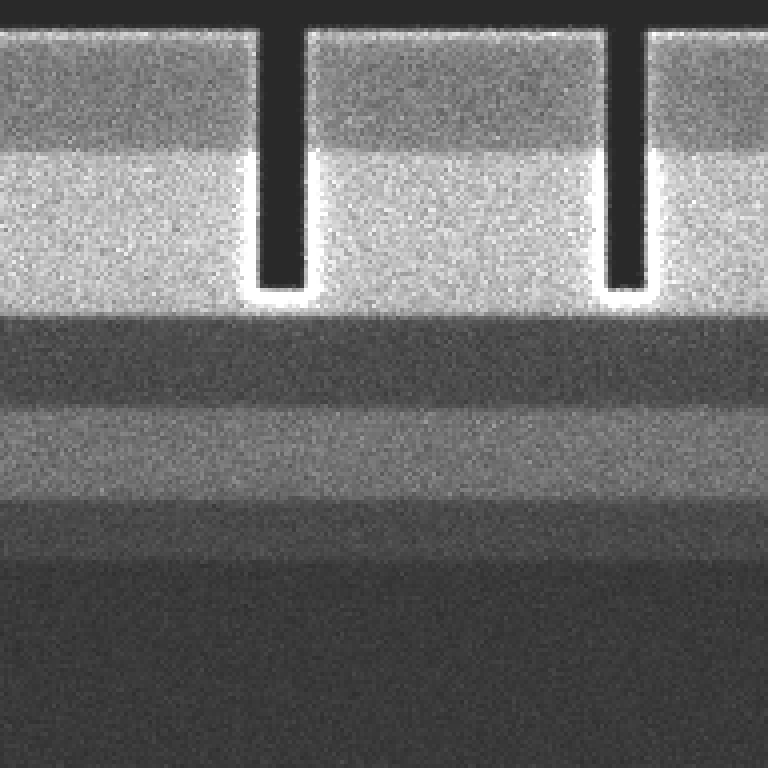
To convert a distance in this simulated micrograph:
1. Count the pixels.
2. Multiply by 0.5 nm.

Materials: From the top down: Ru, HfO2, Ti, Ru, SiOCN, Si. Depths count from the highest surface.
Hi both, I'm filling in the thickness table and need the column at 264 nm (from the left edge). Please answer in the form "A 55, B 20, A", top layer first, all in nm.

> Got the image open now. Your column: Ru 60, HfO2 82, Ti 46, Ru 46, SiOCN 30, Si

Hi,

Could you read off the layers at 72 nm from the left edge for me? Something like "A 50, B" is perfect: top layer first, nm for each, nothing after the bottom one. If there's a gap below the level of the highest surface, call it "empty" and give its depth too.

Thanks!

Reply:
Ru 60, HfO2 82, Ti 46, Ru 46, SiOCN 30, Si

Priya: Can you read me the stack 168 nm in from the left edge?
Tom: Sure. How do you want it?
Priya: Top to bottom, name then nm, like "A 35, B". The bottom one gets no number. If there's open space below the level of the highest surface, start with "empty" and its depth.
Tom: Ru 60, HfO2 82, Ti 46, Ru 46, SiOCN 30, Si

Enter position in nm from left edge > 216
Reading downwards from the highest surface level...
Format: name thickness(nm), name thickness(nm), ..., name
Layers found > Ru 60, HfO2 82, Ti 46, Ru 46, SiOCN 30, Si